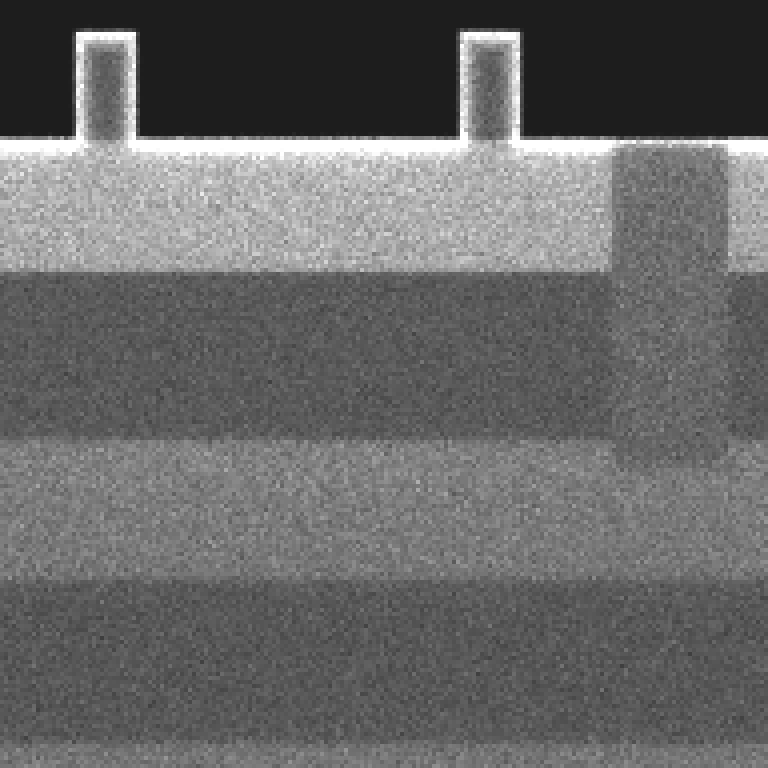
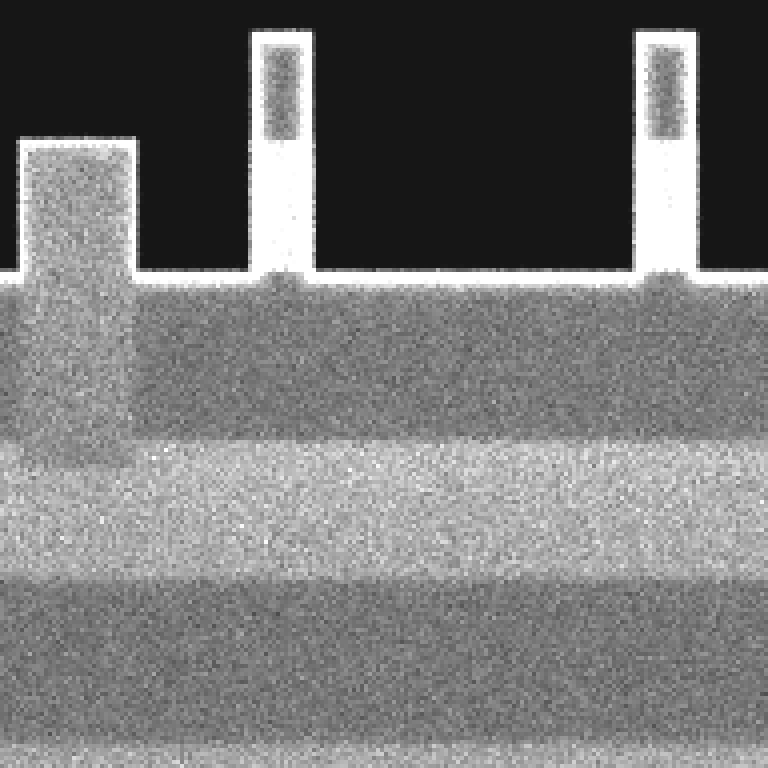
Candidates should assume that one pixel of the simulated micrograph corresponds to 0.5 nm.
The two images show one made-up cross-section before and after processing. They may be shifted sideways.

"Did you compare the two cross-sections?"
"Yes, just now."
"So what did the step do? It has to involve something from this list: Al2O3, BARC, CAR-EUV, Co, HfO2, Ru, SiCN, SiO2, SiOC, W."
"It removed HfO2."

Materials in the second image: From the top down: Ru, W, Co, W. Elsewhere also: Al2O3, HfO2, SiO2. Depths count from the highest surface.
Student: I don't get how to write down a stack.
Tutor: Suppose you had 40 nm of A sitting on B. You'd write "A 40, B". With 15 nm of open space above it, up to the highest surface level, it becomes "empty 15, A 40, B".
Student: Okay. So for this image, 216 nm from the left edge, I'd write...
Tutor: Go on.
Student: empty 120, Al2O3 84, W 70, Co 82, W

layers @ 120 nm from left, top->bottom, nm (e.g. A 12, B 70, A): empty 120, Al2O3 84, W 70, Co 82, W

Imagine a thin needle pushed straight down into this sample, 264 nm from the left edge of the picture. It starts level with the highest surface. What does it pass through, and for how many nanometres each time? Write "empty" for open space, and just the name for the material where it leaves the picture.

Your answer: empty 120, Al2O3 84, W 70, Co 82, W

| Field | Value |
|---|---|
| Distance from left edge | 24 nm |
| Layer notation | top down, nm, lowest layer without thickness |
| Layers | empty 54, Ru 164, W 56, Co 82, W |